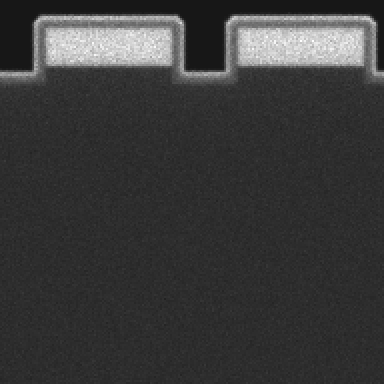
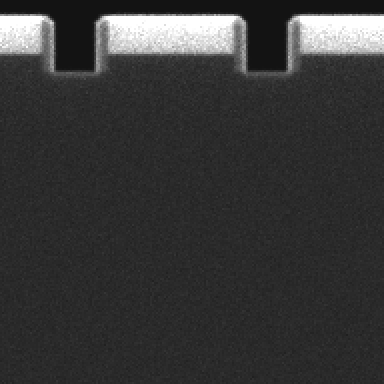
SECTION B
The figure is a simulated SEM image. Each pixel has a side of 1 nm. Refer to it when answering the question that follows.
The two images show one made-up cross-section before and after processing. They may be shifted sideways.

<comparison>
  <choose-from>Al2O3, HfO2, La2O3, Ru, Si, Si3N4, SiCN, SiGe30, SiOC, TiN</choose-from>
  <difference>Si3N4 removed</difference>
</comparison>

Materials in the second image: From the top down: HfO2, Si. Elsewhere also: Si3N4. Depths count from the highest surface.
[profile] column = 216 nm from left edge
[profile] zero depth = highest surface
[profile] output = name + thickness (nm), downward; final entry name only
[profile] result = HfO2 38, Si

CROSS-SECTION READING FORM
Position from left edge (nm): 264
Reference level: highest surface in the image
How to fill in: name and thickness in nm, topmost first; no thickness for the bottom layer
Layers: empty 56, Si